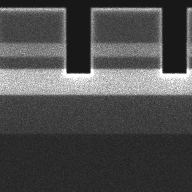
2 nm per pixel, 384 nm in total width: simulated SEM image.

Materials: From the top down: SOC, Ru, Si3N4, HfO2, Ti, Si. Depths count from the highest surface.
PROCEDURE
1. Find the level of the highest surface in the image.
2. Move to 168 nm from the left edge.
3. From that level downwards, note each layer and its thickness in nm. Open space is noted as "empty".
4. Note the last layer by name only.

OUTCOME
empty 132, HfO2 42, Ti 78, Si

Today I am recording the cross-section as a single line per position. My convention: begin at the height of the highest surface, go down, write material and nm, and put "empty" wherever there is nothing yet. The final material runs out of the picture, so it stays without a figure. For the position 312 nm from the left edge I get SOC 70, Ru 28, Si3N4 24, HfO2 52, Ti 78, Si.